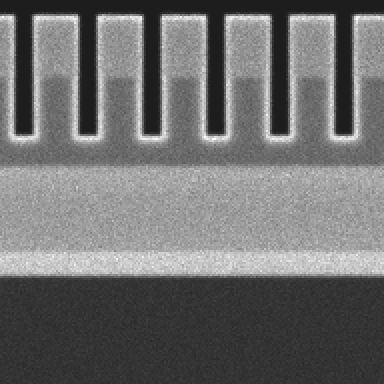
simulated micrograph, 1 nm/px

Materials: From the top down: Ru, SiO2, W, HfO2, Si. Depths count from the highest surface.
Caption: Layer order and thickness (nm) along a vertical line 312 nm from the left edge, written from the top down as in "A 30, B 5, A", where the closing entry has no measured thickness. Ru 62, SiO2 88, W 86, HfO2 24, Si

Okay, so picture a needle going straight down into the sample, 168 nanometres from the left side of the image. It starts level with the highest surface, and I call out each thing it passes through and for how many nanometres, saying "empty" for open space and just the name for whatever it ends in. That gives Ru 62, SiO2 88, W 86, HfO2 24, Si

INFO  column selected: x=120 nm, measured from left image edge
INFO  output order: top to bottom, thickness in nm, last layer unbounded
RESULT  Ru 62, SiO2 88, W 86, HfO2 24, Si